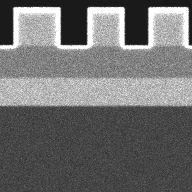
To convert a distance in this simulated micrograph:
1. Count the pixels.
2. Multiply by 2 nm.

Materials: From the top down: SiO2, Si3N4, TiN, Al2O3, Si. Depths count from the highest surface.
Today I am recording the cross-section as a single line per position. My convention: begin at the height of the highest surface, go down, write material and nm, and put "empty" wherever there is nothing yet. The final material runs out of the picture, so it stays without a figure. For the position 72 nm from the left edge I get SiO2 76, Si3N4 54, TiN 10, Al2O3 56, Si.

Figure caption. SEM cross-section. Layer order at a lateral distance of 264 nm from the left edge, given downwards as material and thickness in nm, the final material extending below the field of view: empty 76, Si3N4 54, TiN 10, Al2O3 56, Si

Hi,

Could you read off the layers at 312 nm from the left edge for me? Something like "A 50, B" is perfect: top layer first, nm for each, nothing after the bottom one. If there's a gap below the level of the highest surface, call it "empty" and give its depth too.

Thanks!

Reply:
SiO2 76, Si3N4 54, TiN 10, Al2O3 56, Si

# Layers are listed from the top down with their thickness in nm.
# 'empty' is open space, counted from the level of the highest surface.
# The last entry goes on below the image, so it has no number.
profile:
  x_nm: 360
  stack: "SiO2 76, Si3N4 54, TiN 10, Al2O3 56, Si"